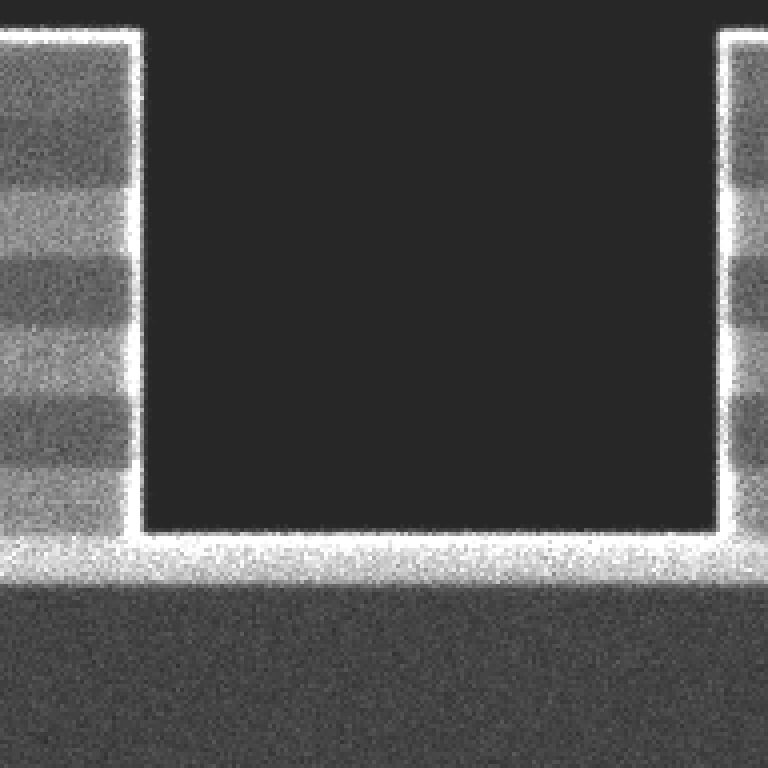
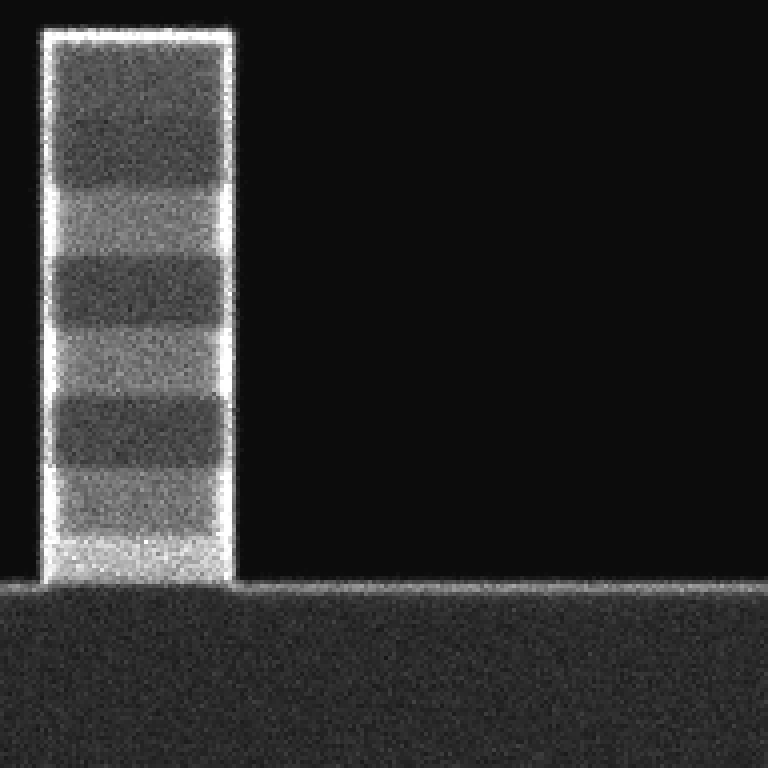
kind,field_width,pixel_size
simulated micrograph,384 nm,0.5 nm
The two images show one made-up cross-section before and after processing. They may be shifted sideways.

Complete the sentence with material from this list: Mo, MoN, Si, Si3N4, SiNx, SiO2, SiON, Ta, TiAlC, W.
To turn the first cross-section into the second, W must be removed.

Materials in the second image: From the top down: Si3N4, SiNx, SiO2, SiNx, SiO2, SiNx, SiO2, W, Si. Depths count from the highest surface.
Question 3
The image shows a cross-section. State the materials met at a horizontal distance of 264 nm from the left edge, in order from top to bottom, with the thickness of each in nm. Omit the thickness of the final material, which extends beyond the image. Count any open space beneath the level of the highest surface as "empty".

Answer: empty 276, Si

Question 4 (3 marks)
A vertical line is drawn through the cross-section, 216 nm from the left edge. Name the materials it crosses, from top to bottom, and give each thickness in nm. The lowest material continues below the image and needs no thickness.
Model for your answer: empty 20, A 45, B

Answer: empty 276, Si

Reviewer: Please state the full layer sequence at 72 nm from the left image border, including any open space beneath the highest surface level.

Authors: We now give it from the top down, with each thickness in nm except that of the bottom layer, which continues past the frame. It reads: Si3N4 42, SiNx 36, SiO2 34, SiNx 36, SiO2 34, SiNx 36, SiO2 34, W 24, Si